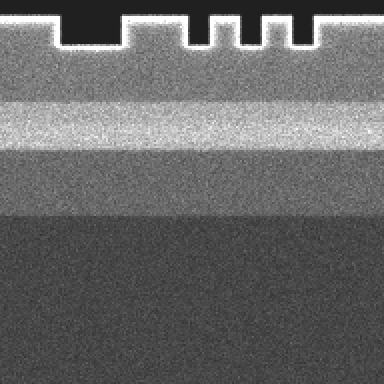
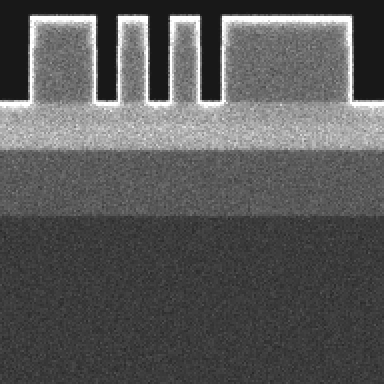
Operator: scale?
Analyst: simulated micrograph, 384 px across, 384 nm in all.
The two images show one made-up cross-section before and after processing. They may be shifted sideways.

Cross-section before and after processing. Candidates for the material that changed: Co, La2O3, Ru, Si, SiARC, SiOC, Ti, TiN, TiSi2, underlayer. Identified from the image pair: TiN (removed).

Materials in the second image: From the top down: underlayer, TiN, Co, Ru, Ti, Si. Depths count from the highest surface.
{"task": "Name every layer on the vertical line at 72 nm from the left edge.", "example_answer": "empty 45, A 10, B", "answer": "underlayer 30, TiN 56, Co 22, Ru 26, Ti 66, Si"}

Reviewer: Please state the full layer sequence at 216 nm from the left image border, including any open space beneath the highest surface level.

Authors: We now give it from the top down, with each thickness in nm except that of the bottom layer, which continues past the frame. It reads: empty 86, Co 22, Ru 26, Ti 66, Si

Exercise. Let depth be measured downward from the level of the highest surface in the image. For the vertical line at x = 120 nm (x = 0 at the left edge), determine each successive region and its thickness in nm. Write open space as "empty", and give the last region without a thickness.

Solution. underlayer 30, TiN 56, Co 22, Ru 26, Ti 66, Si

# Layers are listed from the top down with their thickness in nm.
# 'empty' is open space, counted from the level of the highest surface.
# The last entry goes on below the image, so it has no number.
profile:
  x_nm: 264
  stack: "underlayer 30, TiN 56, Co 22, Ru 26, Ti 66, Si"